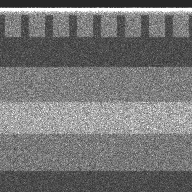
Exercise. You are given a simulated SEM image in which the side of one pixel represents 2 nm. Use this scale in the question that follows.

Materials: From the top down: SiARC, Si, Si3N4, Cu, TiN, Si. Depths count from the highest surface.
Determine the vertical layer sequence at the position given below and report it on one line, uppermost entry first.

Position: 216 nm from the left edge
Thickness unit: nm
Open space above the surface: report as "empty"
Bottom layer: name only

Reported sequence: SiARC 58, Si 60, Si3N4 70, Cu 64, TiN 74, Si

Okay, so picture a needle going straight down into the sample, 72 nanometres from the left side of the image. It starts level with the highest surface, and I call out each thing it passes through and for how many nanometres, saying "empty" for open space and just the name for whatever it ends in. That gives SiARC 58, Si 60, Si3N4 70, Cu 64, TiN 74, Si